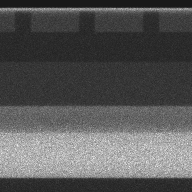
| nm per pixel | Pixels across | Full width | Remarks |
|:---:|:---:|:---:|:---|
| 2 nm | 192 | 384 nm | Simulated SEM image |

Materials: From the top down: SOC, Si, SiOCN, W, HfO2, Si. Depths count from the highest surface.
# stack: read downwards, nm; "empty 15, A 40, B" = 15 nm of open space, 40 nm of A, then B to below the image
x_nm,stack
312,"SOC 6, Si 102, SiOCN 88, W 54, HfO2 90, Si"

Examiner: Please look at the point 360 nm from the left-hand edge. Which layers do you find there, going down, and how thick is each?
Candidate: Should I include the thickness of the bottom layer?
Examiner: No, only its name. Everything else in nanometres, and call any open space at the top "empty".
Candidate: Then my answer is SOC 48, Si 60, SiOCN 88, W 54, HfO2 90, Si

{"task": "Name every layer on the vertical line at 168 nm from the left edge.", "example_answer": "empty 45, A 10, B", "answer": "SOC 6, Si 102, SiOCN 88, W 54, HfO2 90, Si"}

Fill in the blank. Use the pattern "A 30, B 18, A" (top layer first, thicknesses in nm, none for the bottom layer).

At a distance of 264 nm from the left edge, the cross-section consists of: SOC 48, Si 60, SiOCN 88, W 54, HfO2 90, Si